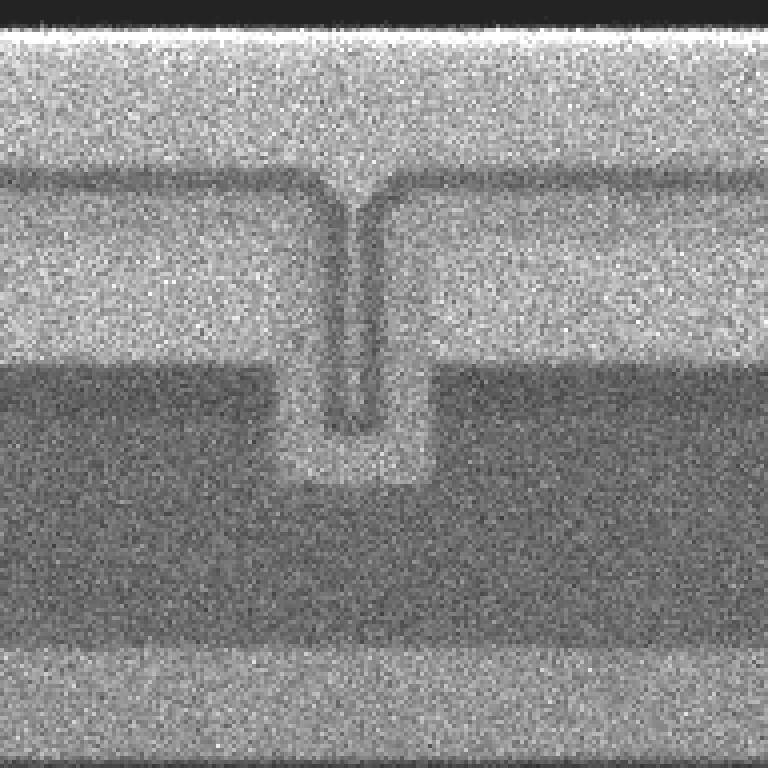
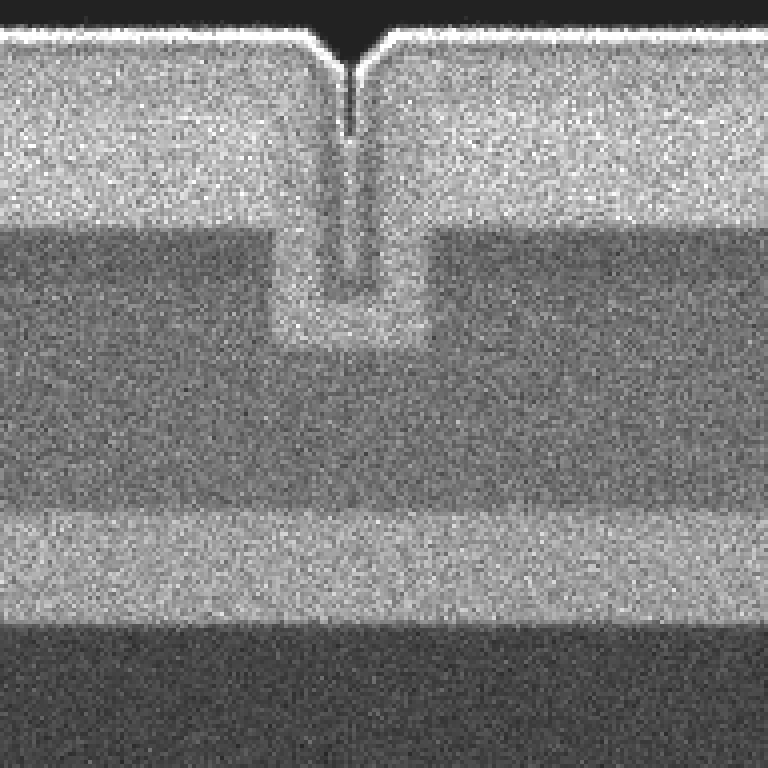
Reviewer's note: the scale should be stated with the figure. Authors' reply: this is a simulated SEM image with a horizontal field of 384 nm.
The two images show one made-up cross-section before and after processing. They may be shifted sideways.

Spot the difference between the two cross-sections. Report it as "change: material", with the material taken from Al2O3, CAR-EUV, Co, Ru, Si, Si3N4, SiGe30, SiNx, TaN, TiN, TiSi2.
removed: Ru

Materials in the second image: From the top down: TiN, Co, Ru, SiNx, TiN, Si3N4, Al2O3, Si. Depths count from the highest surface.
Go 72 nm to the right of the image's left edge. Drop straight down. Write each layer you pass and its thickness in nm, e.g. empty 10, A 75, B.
TiN 12, Co 24, Ru 62, SiNx 26, TiN 50, Si3N4 66, Al2O3 56, Si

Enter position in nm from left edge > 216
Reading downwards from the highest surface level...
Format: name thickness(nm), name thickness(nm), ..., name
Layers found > TiN 12, Co 24, Ru 62, SiNx 26, TiN 50, Si3N4 66, Al2O3 56, Si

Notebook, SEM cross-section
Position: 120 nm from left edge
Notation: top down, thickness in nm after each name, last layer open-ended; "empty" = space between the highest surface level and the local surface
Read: TiN 12, Co 24, Ru 62, SiNx 26, TiN 50, Si3N4 66, Al2O3 56, Si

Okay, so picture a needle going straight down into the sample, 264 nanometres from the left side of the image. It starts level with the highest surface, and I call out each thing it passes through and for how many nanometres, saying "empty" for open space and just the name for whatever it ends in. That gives TiN 12, Co 24, Ru 62, SiNx 26, TiN 50, Si3N4 66, Al2O3 56, Si